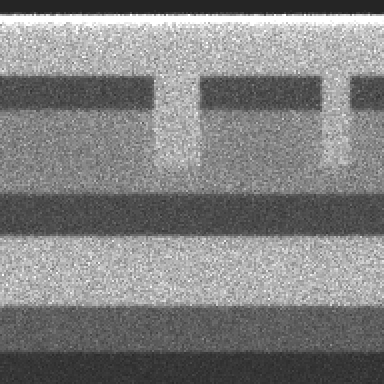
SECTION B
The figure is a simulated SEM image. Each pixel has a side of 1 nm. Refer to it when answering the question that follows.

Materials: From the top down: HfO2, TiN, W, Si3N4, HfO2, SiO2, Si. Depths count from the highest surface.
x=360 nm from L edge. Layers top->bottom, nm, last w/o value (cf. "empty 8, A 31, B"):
HfO2 60, TiN 34, W 84, Si3N4 42, HfO2 70, SiO2 46, Si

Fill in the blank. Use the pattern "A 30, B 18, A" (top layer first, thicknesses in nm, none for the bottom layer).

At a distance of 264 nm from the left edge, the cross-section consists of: HfO2 60, TiN 34, W 84, Si3N4 42, HfO2 70, SiO2 46, Si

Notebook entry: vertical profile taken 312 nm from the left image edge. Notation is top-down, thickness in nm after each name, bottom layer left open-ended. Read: HfO2 60, TiN 34, W 84, Si3N4 42, HfO2 70, SiO2 46, Si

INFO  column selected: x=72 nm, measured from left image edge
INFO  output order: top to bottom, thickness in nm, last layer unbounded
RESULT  HfO2 60, TiN 34, W 84, Si3N4 42, HfO2 70, SiO2 46, Si